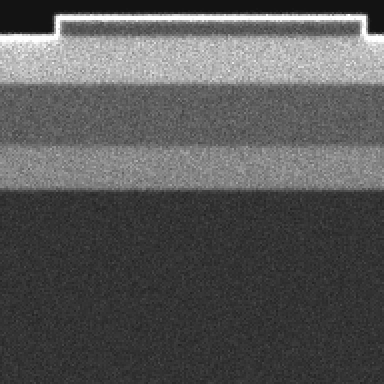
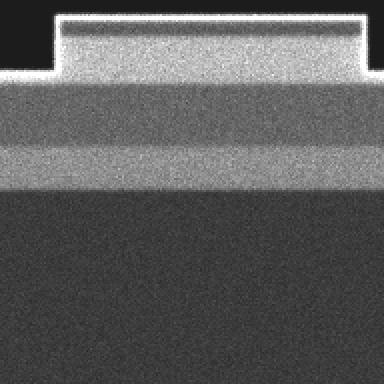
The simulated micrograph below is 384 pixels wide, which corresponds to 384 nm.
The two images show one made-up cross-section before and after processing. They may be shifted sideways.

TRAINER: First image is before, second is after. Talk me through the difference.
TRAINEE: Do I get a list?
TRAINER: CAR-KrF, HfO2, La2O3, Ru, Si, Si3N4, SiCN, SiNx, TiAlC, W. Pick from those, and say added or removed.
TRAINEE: removed: W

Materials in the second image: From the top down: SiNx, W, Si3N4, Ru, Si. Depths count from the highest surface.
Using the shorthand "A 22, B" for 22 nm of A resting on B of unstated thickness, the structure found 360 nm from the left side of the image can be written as SiNx 20, W 48, Si3N4 62, Ru 44, Si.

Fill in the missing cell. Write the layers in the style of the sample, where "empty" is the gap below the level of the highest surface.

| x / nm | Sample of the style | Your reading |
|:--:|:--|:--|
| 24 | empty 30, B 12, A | empty 56, W 12, Si3N4 62, Ru 44, Si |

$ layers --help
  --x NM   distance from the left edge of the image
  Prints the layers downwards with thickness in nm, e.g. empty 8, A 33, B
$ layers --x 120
SiNx 20, W 48, Si3N4 62, Ru 44, Si